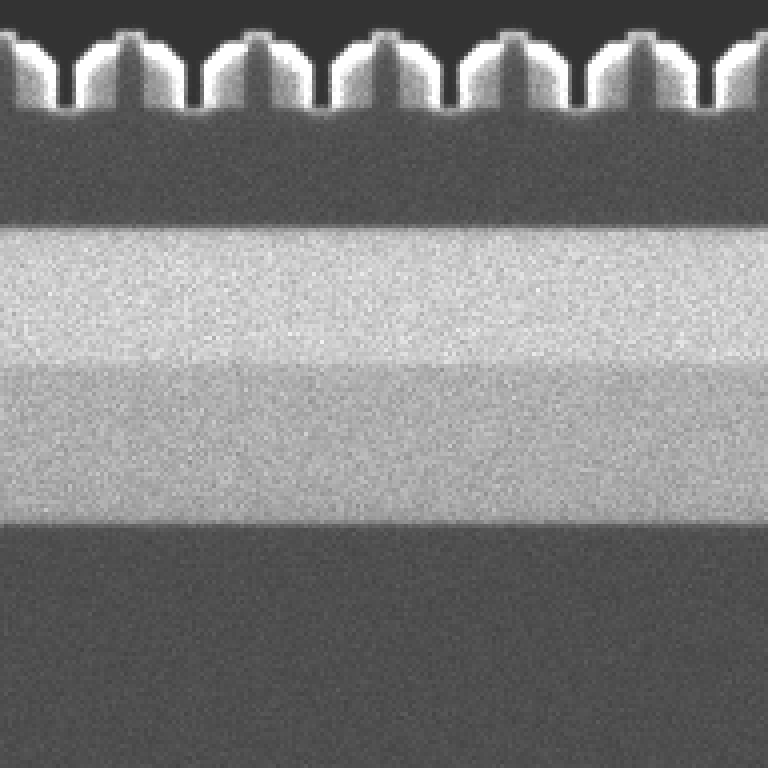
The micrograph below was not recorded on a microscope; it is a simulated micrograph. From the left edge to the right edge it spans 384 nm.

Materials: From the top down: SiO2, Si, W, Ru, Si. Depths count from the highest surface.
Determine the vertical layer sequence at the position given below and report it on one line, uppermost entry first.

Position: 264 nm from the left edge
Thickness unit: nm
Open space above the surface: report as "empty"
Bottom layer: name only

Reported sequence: empty 6, SiO2 32, Si 60, W 68, Ru 80, Si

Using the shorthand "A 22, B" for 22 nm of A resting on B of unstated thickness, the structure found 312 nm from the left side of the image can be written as empty 6, SiO2 32, Si 60, W 68, Ru 80, Si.